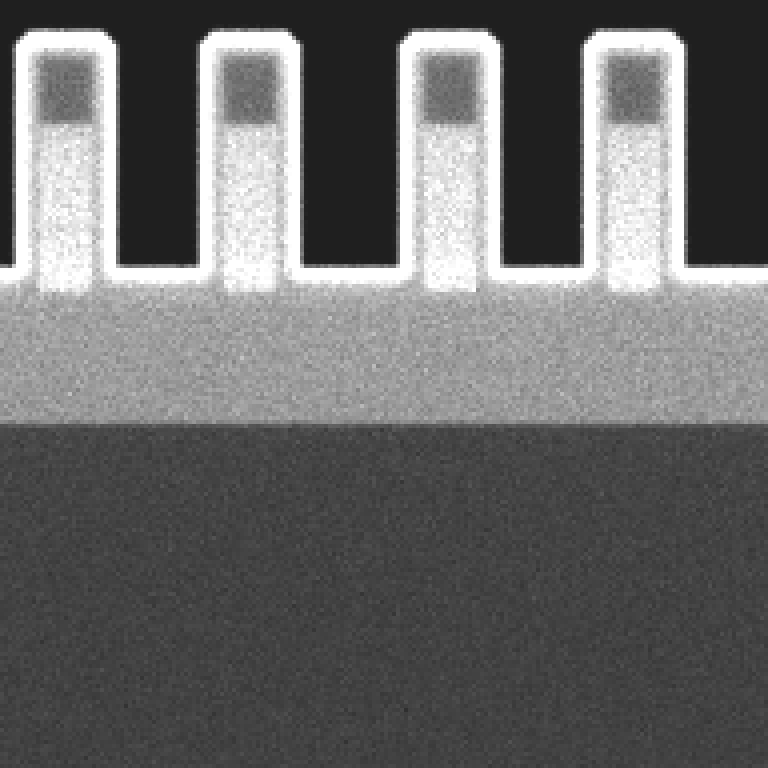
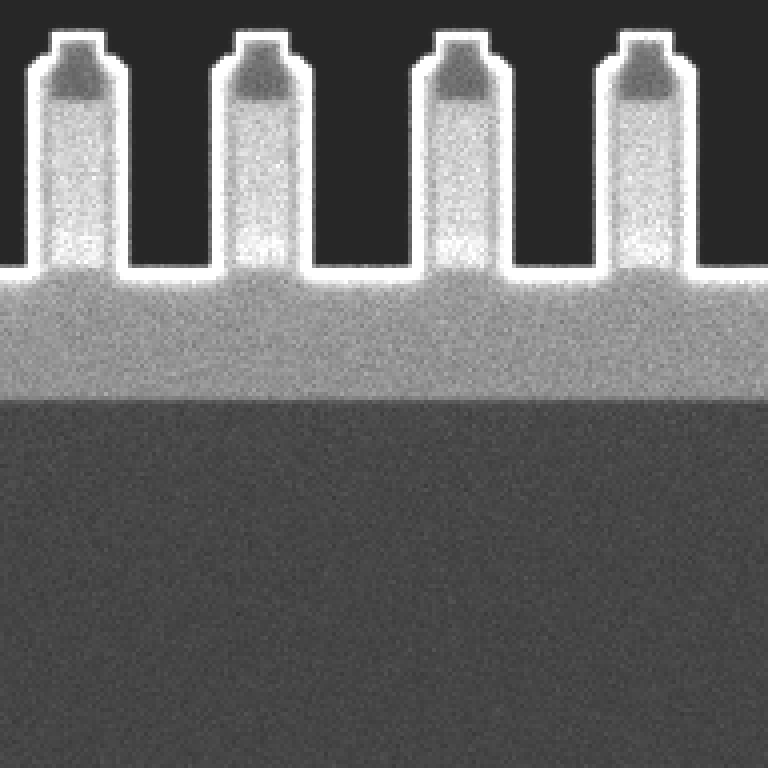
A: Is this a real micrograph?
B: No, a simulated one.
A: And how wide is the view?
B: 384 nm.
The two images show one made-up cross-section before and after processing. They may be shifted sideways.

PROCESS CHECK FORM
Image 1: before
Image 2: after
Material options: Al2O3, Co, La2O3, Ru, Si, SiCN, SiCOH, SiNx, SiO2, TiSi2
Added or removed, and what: removed, SiO2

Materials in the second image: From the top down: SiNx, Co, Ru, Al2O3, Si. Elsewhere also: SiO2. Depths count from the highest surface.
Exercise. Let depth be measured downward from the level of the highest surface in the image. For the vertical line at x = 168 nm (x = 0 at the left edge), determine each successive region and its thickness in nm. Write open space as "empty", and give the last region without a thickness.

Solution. empty 118, Al2O3 66, Si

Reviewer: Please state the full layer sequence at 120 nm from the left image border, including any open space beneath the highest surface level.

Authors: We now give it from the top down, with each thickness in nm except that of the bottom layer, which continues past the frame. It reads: SiNx 34, Co 68, Ru 16, Al2O3 66, Si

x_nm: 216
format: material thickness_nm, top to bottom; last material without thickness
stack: empty 12, SiO2 106, Al2O3 66, Si